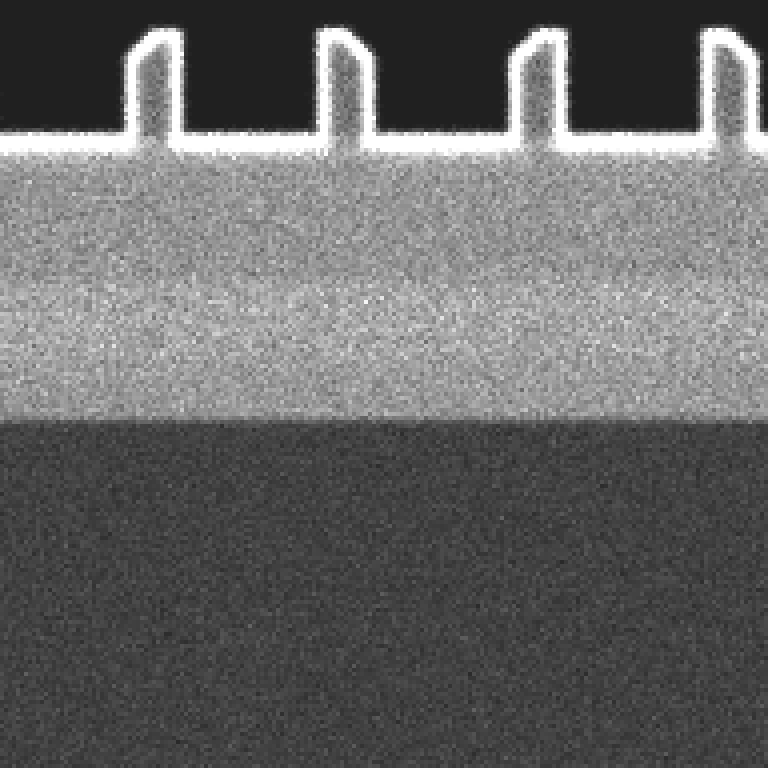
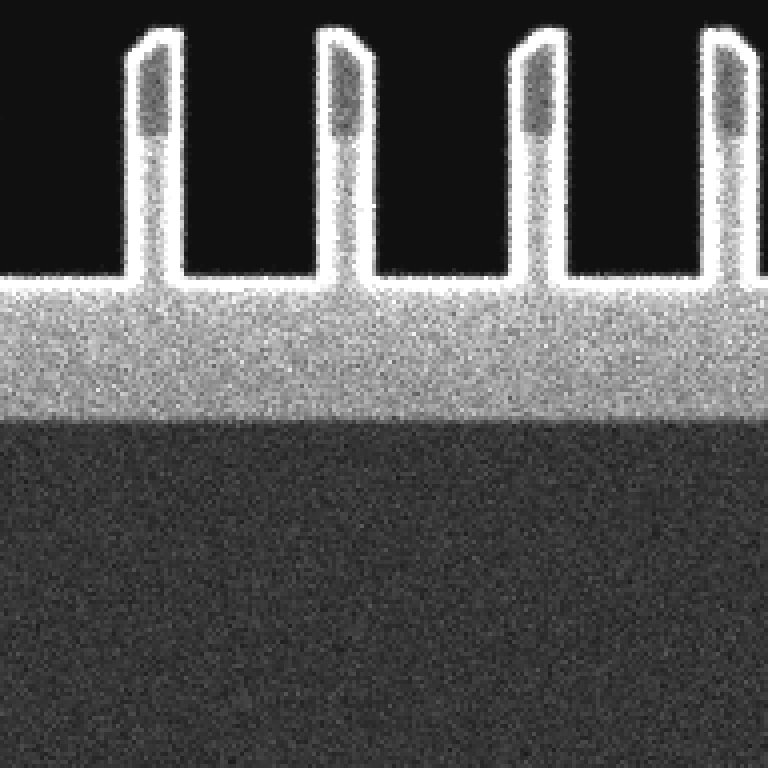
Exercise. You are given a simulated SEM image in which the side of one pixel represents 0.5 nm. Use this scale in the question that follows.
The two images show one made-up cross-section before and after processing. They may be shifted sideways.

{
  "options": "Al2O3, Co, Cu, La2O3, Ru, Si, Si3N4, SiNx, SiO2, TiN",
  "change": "removed",
  "material": "SiO2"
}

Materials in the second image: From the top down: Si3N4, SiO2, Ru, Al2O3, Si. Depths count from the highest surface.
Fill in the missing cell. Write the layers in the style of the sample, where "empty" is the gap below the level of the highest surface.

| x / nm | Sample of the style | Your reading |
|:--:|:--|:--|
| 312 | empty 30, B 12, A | empty 124, Ru 44, Al2O3 26, Si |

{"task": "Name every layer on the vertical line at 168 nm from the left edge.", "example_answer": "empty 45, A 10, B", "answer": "Si3N4 52, SiO2 72, Ru 44, Al2O3 26, Si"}